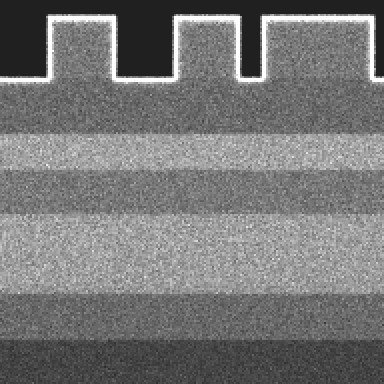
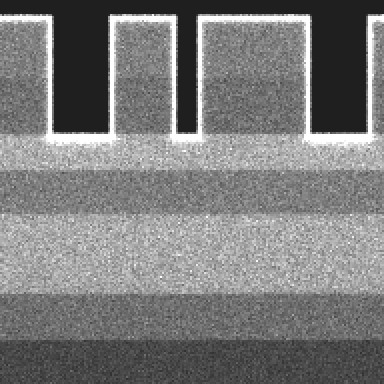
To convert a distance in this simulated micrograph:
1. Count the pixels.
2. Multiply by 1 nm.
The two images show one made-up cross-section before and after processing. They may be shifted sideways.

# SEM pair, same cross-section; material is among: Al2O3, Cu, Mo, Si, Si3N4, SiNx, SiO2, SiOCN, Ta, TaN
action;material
removed;SiNx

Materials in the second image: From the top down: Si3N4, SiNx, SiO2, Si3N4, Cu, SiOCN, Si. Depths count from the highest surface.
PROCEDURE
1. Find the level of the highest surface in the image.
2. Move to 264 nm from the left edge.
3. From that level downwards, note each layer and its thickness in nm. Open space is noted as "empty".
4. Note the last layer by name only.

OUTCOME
Si3N4 62, SiNx 56, SiO2 36, Si3N4 44, Cu 80, SiOCN 46, Si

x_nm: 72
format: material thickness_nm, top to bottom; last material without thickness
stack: empty 118, SiO2 36, Si3N4 44, Cu 80, SiOCN 46, Si